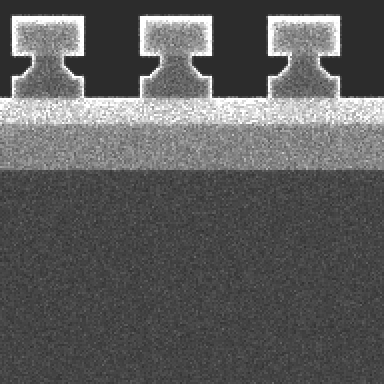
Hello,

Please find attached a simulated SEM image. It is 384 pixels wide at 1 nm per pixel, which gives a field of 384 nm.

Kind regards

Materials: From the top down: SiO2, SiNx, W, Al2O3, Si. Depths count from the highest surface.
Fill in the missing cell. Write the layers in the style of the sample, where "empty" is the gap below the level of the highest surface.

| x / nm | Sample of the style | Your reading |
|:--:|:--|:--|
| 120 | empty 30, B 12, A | empty 82, W 26, Al2O3 46, Si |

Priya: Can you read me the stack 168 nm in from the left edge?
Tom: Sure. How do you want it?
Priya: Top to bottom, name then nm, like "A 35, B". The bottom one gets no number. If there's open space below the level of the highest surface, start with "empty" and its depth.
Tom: SiO2 40, SiNx 42, W 26, Al2O3 46, Si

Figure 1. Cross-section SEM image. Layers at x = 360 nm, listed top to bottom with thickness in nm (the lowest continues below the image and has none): empty 82, W 26, Al2O3 46, Si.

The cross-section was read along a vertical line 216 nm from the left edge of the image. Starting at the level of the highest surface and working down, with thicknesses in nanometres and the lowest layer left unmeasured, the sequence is empty 82, W 26, Al2O3 46, Si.